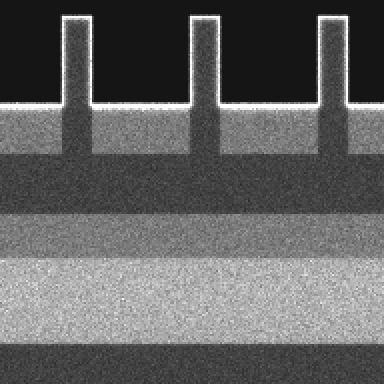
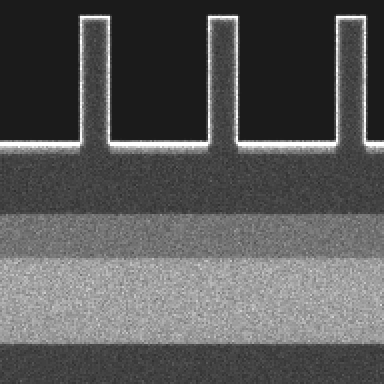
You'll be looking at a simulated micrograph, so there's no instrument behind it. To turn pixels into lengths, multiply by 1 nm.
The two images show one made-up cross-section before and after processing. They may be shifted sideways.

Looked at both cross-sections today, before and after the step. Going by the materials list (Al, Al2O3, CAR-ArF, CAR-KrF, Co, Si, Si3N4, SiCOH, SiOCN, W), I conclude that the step removed Si3N4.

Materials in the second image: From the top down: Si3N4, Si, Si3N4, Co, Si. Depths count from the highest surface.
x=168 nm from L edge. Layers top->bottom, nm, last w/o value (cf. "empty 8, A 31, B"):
empty 126, Si3N4 12, Si 60, Si3N4 44, Co 86, Si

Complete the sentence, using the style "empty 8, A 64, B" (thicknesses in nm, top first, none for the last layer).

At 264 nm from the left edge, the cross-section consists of empty 126, Si3N4 12, Si 60, Si3N4 44, Co 86, Si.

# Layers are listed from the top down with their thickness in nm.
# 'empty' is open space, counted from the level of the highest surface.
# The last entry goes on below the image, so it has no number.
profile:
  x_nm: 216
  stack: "Si 198, Si3N4 44, Co 86, Si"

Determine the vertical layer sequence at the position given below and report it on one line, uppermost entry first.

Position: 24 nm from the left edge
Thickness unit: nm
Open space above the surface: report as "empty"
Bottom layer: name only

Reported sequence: empty 126, Si3N4 12, Si 60, Si3N4 44, Co 86, Si